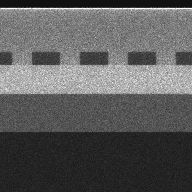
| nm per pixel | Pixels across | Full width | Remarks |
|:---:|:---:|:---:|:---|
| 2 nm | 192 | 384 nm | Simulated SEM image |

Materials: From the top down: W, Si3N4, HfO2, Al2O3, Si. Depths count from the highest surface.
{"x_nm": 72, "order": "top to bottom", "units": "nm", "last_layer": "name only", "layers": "W 88, Si3N4 26, HfO2 58, Al2O3 76, Si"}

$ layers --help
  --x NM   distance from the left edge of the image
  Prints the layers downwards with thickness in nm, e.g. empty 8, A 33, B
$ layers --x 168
W 88, Si3N4 26, HfO2 58, Al2O3 76, Si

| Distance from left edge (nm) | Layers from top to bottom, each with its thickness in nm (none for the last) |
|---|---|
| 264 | W 88, Si3N4 26, HfO2 58, Al2O3 76, Si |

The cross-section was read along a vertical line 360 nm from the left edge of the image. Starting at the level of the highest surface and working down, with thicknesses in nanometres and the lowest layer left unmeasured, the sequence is W 88, Si3N4 26, HfO2 58, Al2O3 76, Si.